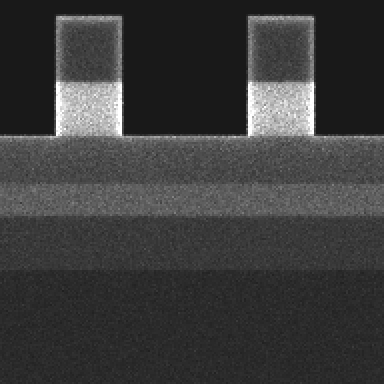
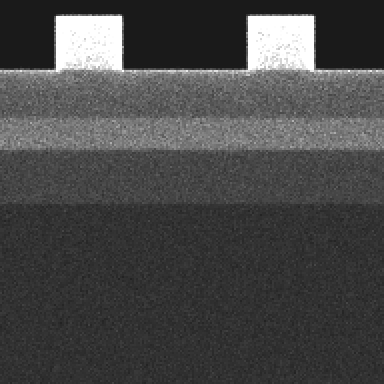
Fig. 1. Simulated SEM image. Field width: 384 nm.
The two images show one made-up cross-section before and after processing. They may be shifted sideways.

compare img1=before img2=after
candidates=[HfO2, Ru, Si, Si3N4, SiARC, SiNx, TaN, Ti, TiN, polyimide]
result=removed:SiARC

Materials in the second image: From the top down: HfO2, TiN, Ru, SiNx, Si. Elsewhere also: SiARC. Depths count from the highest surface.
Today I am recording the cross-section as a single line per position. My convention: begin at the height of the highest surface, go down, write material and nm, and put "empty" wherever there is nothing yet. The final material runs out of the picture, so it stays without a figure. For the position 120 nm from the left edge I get HfO2 54, TiN 48, Ru 32, SiNx 54, Si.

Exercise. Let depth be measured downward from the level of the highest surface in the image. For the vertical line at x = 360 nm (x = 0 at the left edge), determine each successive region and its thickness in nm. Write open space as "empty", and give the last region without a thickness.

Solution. empty 54, TiN 48, Ru 32, SiNx 54, Si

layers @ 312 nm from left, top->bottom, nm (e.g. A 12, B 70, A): HfO2 54, TiN 48, Ru 32, SiNx 54, Si